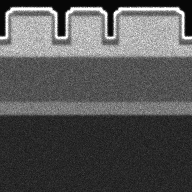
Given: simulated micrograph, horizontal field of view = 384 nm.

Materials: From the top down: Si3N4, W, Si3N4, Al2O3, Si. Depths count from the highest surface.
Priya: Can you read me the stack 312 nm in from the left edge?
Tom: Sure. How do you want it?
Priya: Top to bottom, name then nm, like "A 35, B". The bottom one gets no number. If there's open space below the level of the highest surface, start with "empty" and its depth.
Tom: Si3N4 16, W 82, Si3N4 90, Al2O3 26, Si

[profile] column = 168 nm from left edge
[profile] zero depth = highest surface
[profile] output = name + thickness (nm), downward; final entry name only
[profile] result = Si3N4 16, W 82, Si3N4 90, Al2O3 26, Si